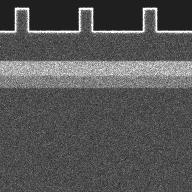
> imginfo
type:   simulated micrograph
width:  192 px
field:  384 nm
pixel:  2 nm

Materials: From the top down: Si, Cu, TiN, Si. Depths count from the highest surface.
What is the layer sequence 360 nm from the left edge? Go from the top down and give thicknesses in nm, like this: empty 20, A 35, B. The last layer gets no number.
empty 46, Si 60, Cu 30, TiN 24, Si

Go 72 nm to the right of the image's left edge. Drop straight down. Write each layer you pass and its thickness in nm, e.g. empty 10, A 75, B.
empty 46, Si 60, Cu 30, TiN 24, Si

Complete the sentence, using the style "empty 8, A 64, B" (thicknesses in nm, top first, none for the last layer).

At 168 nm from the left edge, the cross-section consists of Si 106, Cu 30, TiN 24, Si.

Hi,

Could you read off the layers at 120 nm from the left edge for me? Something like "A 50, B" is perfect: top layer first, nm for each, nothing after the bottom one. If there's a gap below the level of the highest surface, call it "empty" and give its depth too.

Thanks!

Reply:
empty 46, Si 60, Cu 30, TiN 24, Si